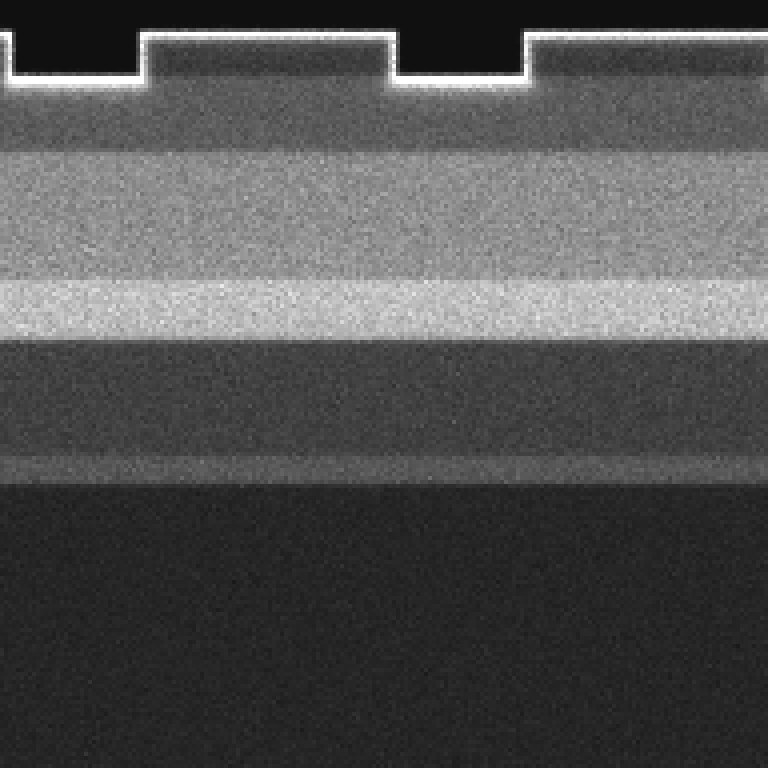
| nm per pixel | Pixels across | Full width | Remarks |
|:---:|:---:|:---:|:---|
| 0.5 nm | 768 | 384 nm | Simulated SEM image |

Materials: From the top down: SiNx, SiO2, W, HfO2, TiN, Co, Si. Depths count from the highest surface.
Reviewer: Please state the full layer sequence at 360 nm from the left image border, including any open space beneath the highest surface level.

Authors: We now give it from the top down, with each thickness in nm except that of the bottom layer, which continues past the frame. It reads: SiNx 22, SiO2 38, W 64, HfO2 30, TiN 58, Co 14, Si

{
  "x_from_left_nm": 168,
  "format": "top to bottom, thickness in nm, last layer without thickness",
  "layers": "SiNx 22, SiO2 38, W 64, HfO2 30, TiN 58, Co 14, Si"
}